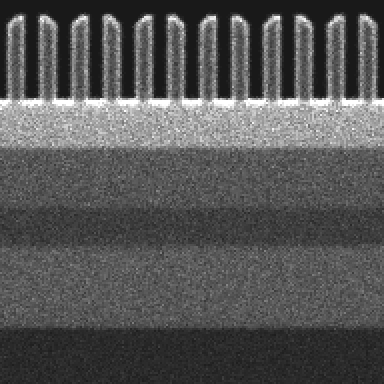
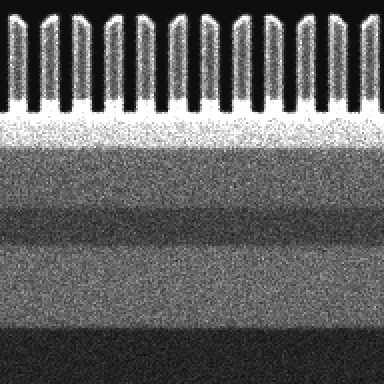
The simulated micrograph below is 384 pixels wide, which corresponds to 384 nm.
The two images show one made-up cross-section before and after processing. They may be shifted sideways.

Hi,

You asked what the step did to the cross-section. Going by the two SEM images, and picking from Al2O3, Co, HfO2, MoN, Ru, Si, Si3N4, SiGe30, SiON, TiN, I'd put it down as HfO2, removed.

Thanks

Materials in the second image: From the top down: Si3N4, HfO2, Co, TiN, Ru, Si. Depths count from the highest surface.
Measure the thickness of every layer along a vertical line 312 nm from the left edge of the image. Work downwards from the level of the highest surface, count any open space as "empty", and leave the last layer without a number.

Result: Si3N4 84, HfO2 48, Co 60, TiN 38, Ru 82, Si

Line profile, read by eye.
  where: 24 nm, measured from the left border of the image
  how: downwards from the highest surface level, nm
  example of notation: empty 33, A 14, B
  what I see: empty 8, Si3N4 76, HfO2 48, Co 60, TiN 38, Ru 82, Si